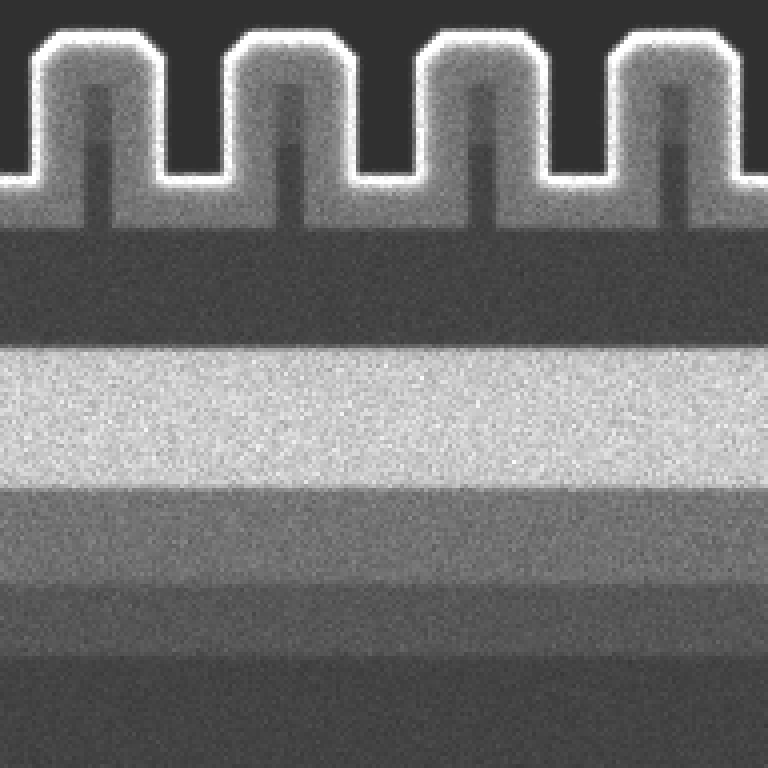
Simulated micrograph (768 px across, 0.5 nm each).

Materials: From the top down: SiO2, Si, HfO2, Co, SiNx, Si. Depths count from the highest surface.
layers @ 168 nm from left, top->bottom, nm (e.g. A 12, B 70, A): empty 4, SiO2 94, Si 60, HfO2 70, Co 48, SiNx 36, Si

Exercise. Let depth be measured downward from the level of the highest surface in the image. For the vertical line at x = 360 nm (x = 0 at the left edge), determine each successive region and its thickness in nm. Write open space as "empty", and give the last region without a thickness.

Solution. empty 4, SiO2 94, Si 60, HfO2 70, Co 48, SiNx 36, Si